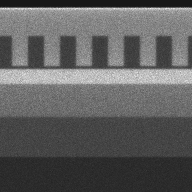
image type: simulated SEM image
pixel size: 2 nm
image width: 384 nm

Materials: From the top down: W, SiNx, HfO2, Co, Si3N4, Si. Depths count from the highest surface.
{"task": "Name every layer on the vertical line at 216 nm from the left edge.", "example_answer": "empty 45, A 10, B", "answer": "W 116, SiNx 6, HfO2 30, Co 66, Si3N4 80, Si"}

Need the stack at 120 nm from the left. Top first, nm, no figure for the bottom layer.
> W 56, SiNx 66, HfO2 30, Co 66, Si3N4 80, Si